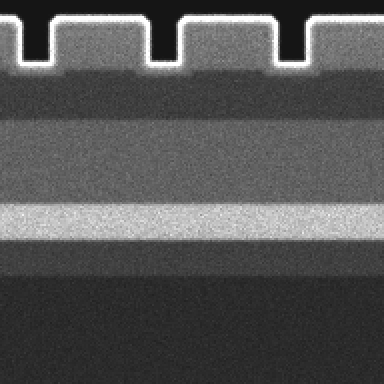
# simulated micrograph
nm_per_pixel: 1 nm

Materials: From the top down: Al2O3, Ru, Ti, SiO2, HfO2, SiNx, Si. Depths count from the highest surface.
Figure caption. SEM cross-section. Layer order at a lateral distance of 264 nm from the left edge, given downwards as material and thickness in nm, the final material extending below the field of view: Al2O3 60, Ti 44, SiO2 84, HfO2 36, SiNx 36, Si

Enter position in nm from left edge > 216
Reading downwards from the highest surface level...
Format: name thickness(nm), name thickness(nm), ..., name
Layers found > Al2O3 14, Ru 40, Ti 50, SiO2 84, HfO2 36, SiNx 36, Si